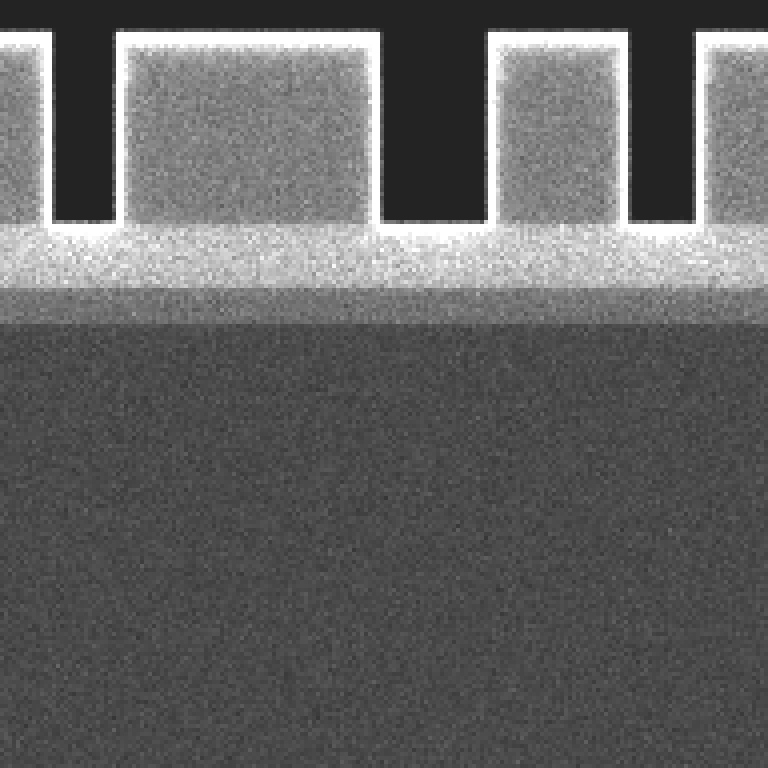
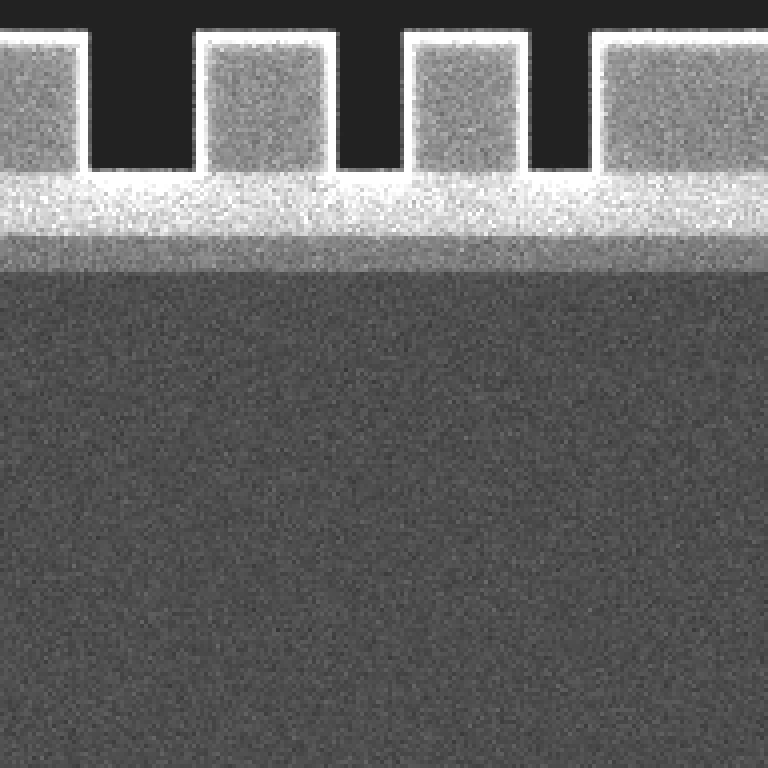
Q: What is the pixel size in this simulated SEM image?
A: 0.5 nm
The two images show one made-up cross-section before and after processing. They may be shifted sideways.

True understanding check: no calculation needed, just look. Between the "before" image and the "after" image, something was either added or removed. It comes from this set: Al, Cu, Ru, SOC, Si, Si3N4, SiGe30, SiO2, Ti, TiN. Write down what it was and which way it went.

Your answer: SOC (removed)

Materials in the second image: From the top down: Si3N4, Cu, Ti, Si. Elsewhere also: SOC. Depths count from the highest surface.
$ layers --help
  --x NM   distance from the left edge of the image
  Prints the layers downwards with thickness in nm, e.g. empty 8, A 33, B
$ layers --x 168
empty 70, Cu 32, Ti 18, Si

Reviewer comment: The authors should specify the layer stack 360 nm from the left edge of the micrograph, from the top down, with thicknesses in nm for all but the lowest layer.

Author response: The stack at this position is Si3N4 70, Cu 32, Ti 18, Si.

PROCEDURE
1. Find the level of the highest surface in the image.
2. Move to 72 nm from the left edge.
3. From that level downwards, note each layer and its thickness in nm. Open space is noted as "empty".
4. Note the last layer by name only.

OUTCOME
empty 70, Cu 32, Ti 18, Si